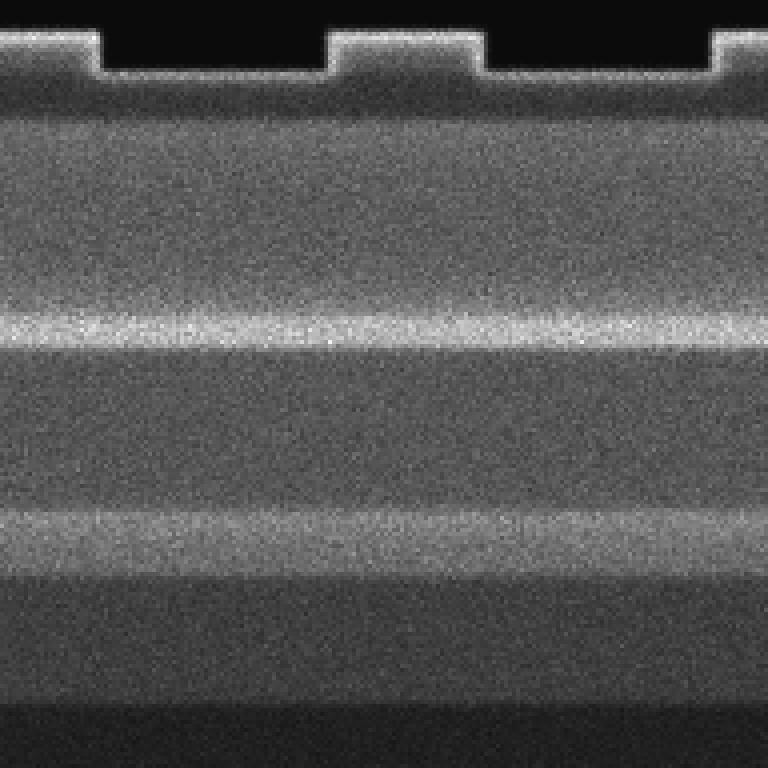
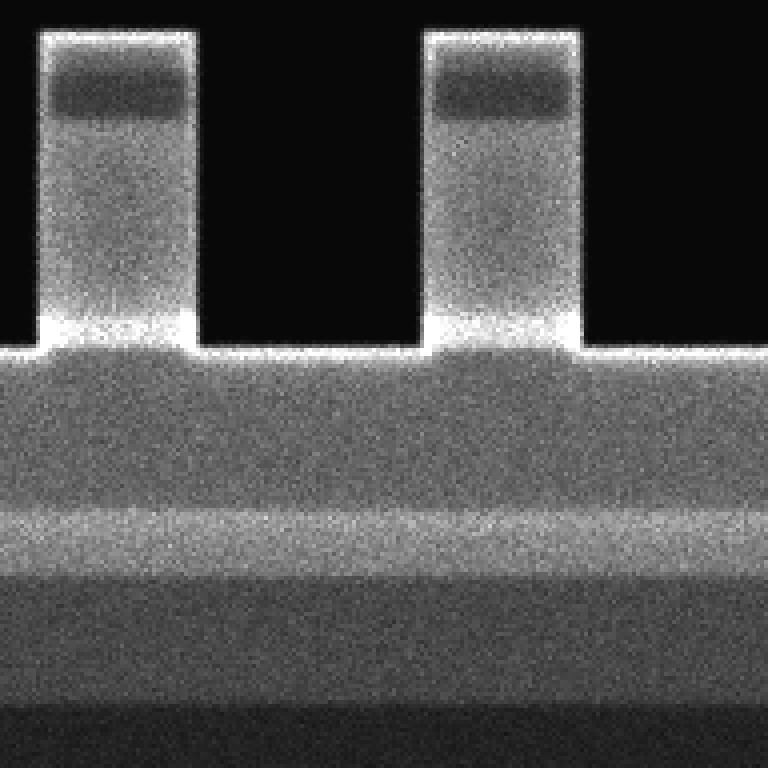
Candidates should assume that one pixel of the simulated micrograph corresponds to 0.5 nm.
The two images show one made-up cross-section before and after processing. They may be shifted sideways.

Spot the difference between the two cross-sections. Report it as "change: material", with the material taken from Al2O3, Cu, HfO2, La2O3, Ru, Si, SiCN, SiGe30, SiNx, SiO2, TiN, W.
removed: HfO2 and Ru and SiNx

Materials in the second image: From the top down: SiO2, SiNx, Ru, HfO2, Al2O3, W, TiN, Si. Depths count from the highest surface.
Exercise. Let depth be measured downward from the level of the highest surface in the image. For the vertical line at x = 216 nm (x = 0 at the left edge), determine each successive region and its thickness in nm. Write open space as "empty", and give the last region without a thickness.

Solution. SiO2 20, SiNx 24, Ru 98, HfO2 16, Al2O3 82, W 32, TiN 64, Si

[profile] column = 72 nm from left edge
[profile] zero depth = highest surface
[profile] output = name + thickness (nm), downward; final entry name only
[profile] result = SiO2 20, SiNx 24, Ru 98, HfO2 16, Al2O3 82, W 32, TiN 64, Si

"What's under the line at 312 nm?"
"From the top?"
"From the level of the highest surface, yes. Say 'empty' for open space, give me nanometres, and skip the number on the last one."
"empty 158, Al2O3 82, W 32, TiN 64, Si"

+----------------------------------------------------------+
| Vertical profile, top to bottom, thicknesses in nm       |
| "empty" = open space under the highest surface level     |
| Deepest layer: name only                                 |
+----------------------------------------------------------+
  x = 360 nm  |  empty 158, Al2O3 82, W 32, TiN 64, Si